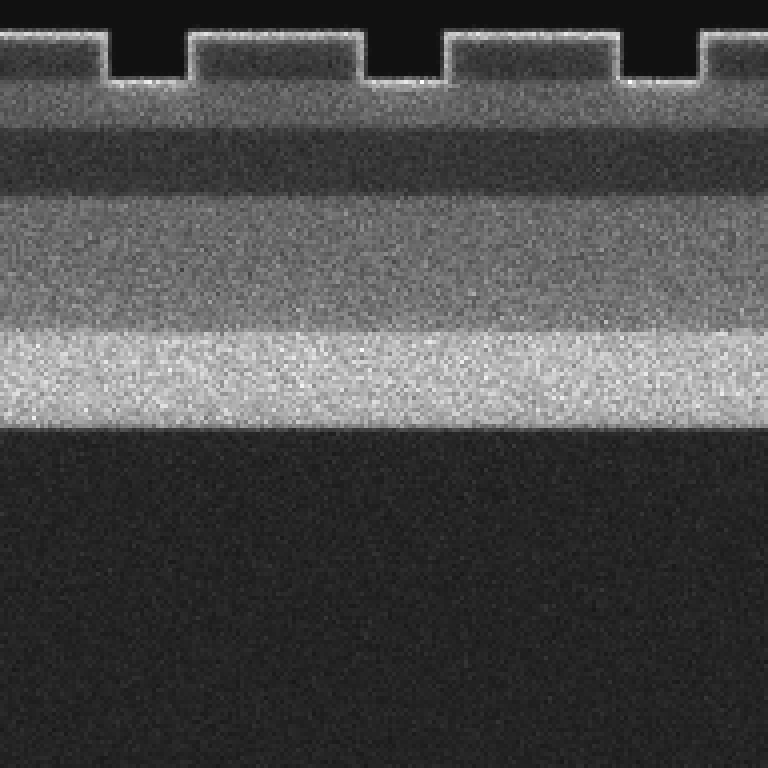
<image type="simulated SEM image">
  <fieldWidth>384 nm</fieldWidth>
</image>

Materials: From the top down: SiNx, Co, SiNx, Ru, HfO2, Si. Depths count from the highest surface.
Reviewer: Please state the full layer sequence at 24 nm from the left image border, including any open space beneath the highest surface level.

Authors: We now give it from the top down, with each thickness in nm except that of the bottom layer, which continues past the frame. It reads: SiNx 24, Co 24, SiNx 34, Ru 68, HfO2 48, Si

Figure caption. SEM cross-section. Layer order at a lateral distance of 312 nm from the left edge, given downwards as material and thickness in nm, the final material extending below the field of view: empty 24, Co 24, SiNx 34, Ru 68, HfO2 48, Si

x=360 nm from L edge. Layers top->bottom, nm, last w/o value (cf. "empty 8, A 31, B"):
SiNx 24, Co 24, SiNx 34, Ru 68, HfO2 48, Si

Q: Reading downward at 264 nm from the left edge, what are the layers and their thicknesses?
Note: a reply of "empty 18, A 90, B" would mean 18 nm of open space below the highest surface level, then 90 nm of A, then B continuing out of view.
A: SiNx 24, Co 24, SiNx 34, Ru 68, HfO2 48, Si